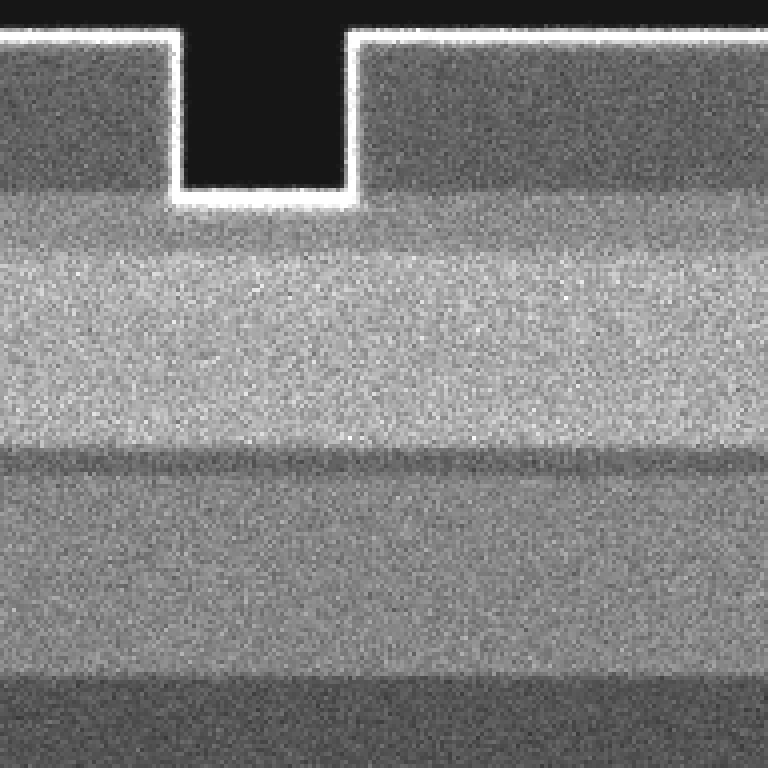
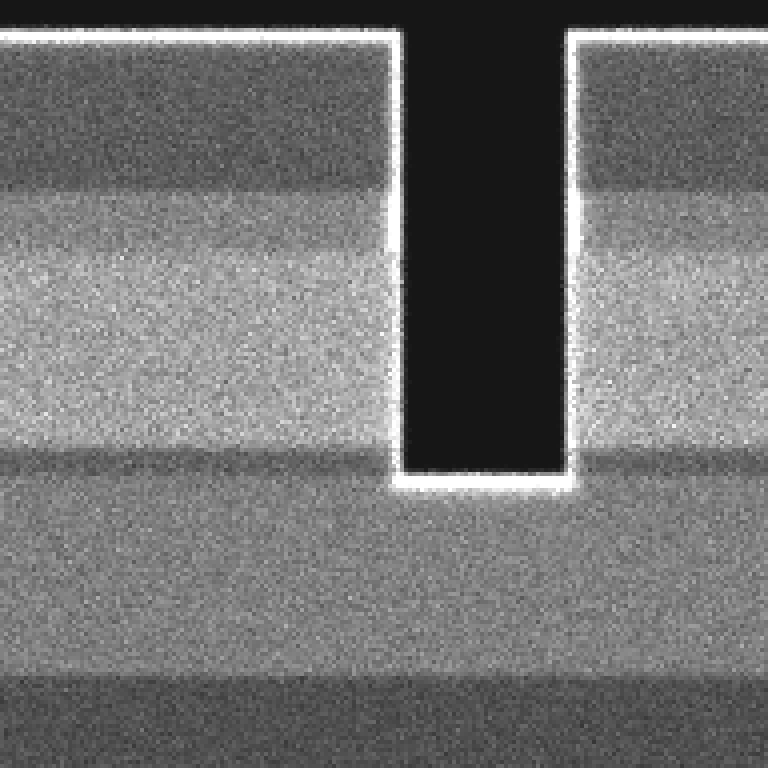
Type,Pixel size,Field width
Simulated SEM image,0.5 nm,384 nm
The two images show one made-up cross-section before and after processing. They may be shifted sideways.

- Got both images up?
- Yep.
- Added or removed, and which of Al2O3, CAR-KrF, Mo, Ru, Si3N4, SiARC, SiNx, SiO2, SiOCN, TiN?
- removed, Al2O3 and Ru and TiN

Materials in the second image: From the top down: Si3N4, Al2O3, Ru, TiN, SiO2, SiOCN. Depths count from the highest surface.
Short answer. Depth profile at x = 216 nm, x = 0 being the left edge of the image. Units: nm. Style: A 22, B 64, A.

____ empty 222, SiO2 100, SiOCN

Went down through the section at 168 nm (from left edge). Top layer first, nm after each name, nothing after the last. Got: Si3N4 80, Al2O3 30, Ru 98, TiN 14, SiO2 100, SiOCN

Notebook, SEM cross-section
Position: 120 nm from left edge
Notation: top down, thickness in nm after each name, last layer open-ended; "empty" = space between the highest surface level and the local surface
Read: Si3N4 80, Al2O3 30, Ru 98, TiN 14, SiO2 100, SiOCN